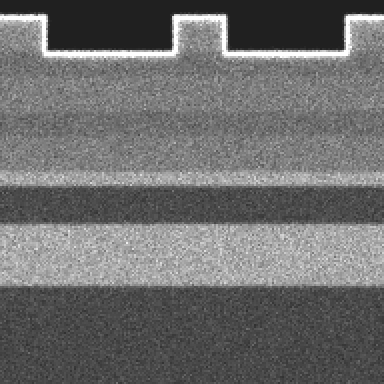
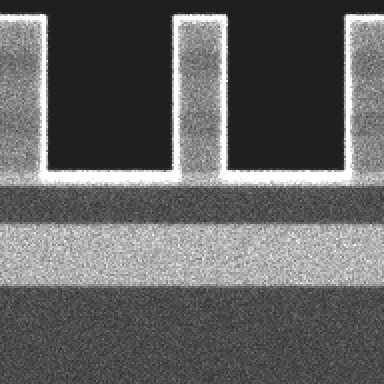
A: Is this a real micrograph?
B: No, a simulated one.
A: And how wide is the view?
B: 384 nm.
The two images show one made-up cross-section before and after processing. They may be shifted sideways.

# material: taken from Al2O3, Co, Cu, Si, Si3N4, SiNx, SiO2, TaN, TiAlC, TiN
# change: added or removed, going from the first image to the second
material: Si3N4 and SiNx
change: removed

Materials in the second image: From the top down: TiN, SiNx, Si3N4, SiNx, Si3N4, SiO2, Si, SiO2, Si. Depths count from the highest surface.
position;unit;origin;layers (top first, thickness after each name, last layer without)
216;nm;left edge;TiN 36, SiNx 24, Si3N4 36, SiNx 24, Si3N4 36, SiO2 14, Si 38, SiO2 62, Si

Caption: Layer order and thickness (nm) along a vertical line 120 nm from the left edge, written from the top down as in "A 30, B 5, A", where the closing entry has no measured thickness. empty 156, SiO2 14, Si 38, SiO2 62, Si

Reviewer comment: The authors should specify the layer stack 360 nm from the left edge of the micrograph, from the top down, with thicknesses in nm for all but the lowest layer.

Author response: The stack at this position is TiN 36, SiNx 24, Si3N4 36, SiNx 24, Si3N4 36, SiO2 14, Si 38, SiO2 62, Si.